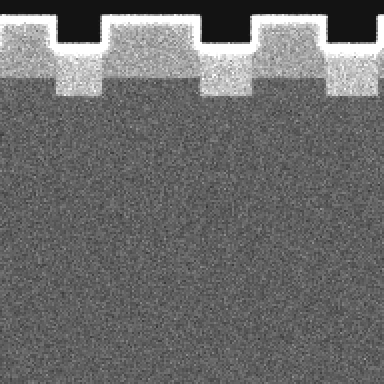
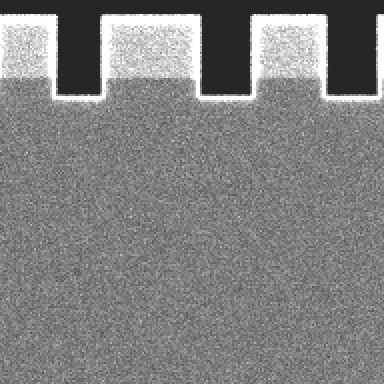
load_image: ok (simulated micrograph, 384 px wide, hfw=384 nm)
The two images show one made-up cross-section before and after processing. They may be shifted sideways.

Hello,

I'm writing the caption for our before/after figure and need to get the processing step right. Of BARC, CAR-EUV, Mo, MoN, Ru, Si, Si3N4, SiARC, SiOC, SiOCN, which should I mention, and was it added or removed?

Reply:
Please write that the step removed SiARC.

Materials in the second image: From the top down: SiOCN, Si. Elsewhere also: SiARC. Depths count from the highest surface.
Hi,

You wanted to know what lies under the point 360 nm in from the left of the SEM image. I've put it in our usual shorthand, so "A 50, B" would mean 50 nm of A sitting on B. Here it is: empty 80, Si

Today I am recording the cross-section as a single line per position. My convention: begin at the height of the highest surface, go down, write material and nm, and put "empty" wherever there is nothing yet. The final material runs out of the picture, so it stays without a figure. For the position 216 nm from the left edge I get empty 80, Si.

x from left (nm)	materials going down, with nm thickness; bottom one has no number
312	SiOCN 62, Si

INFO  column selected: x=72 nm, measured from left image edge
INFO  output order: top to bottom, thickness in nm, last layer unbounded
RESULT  empty 80, Si